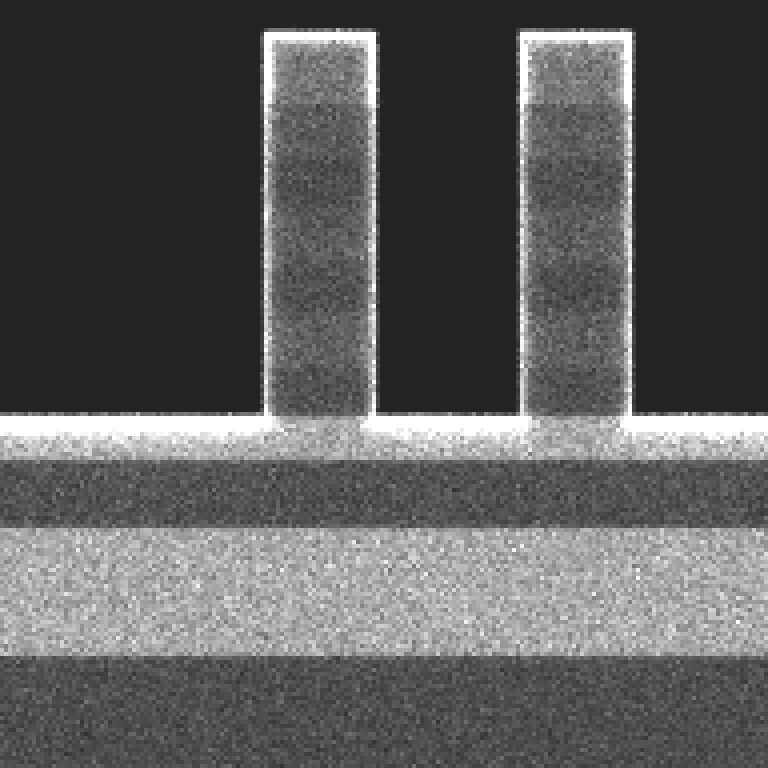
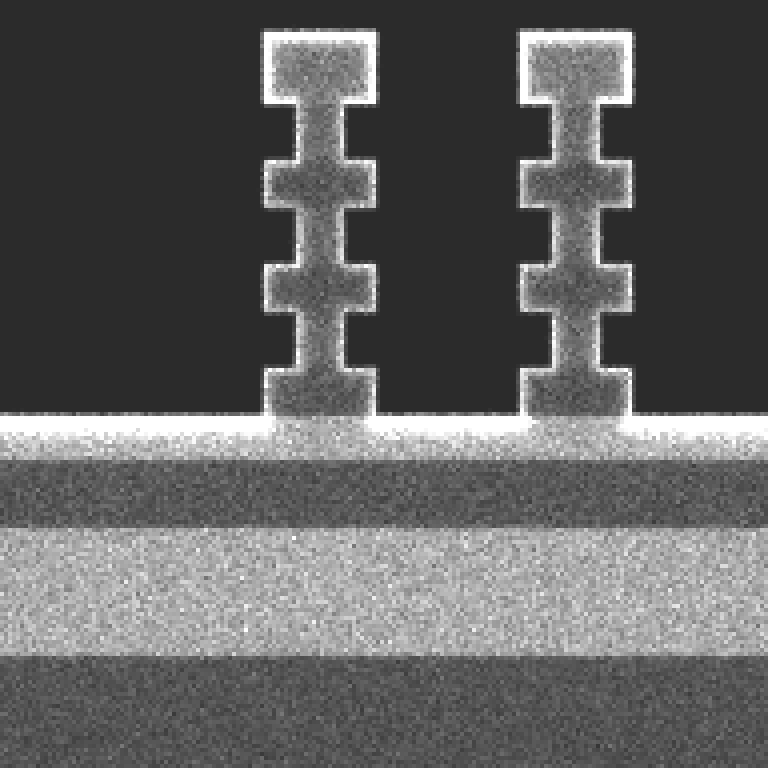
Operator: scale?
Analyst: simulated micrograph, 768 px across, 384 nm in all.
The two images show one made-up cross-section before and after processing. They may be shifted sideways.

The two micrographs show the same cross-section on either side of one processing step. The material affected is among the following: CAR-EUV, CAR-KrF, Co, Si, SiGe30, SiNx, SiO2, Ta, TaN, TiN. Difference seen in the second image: SiGe30 removed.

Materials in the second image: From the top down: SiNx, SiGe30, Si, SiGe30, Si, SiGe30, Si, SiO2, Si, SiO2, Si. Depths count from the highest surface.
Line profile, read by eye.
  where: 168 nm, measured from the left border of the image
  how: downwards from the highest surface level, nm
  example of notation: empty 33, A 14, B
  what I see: SiNx 36, SiGe30 28, Si 24, SiGe30 28, Si 24, SiGe30 28, Si 24, SiO2 22, Si 34, SiO2 64, Si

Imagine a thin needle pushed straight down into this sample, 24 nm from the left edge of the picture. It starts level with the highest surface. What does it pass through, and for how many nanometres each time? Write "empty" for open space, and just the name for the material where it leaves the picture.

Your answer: empty 192, SiO2 22, Si 34, SiO2 64, Si